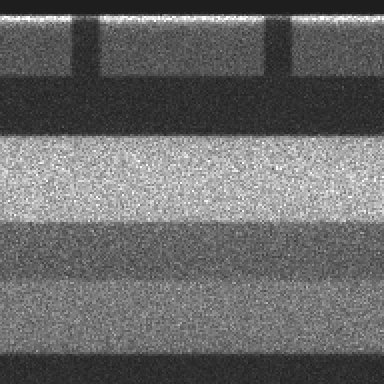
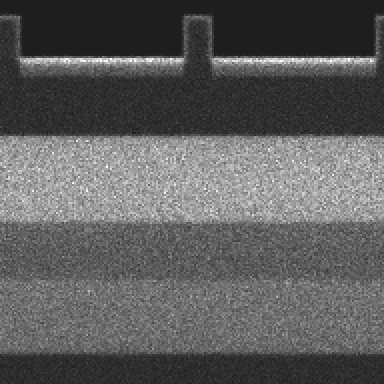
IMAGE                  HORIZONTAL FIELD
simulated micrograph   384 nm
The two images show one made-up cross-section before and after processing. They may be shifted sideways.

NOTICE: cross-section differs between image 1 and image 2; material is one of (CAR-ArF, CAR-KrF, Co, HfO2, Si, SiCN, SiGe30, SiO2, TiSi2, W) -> removed: SiO2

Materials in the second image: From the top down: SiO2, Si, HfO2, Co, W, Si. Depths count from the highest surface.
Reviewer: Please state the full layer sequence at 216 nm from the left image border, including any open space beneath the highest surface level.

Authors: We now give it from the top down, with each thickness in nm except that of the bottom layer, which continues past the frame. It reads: empty 42, SiO2 18, Si 60, HfO2 86, Co 58, W 74, Si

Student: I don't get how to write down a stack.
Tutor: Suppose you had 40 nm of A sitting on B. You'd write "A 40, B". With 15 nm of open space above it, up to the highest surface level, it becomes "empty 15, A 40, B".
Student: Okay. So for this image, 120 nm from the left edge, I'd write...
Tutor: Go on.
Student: empty 42, SiO2 18, Si 60, HfO2 86, Co 58, W 74, Si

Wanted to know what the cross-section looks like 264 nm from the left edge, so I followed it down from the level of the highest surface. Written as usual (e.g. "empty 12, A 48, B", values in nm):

empty 42, SiO2 18, Si 60, HfO2 86, Co 58, W 74, Si